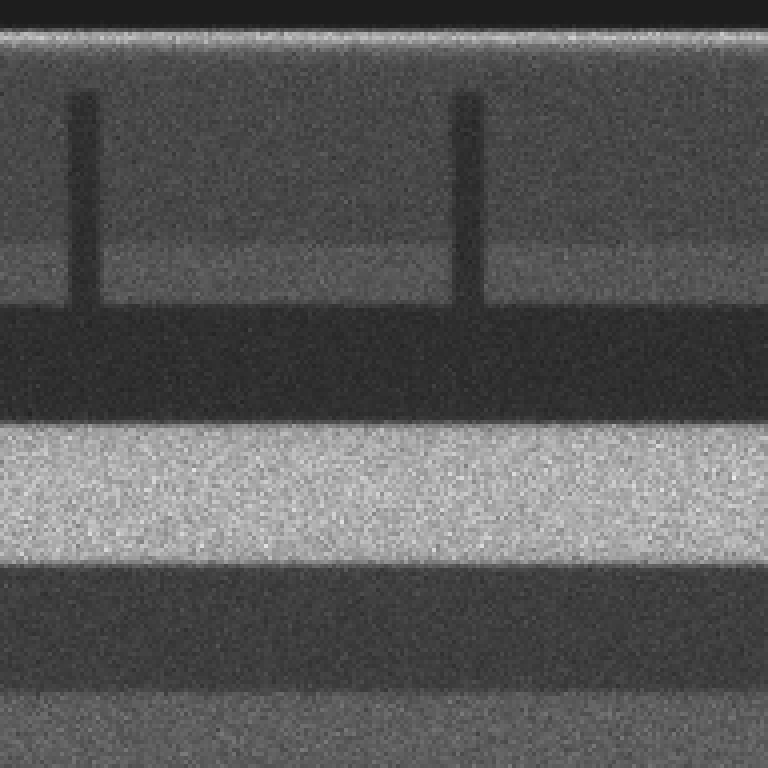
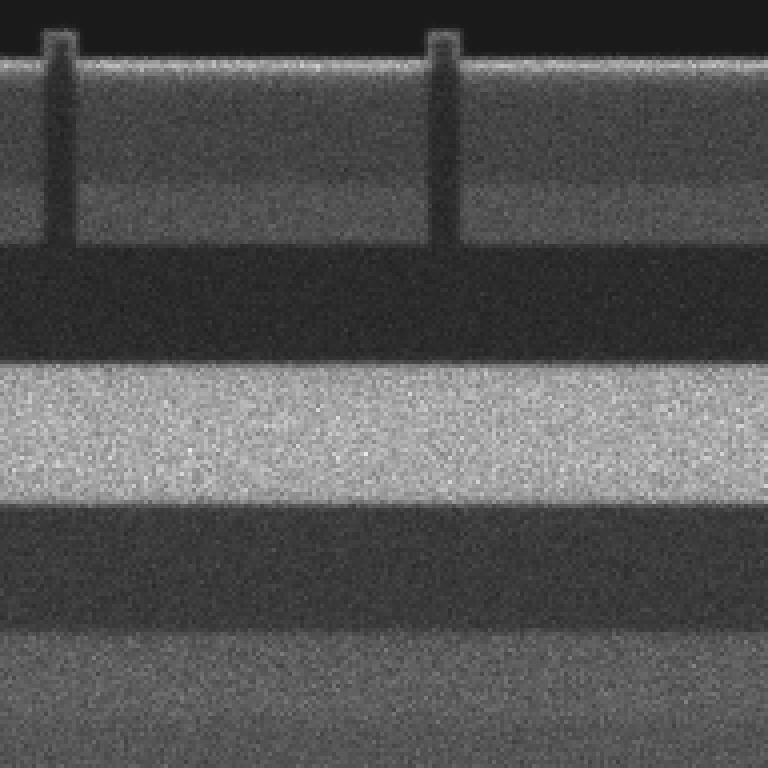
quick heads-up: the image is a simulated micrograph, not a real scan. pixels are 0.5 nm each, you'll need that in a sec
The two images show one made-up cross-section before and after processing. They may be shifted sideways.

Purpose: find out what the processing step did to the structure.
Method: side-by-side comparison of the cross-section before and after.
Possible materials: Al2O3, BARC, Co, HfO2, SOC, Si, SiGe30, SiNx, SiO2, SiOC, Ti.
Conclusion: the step removed SOC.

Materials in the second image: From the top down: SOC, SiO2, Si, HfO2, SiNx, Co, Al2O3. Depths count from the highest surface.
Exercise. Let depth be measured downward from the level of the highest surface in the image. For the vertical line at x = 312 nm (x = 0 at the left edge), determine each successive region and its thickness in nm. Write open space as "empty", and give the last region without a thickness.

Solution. empty 14, SOC 62, SiO2 30, Si 60, HfO2 70, SiNx 64, Co 44, Al2O3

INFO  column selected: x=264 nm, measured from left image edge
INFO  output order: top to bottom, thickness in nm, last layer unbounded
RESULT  empty 14, SOC 62, SiO2 30, Si 60, HfO2 70, SiNx 64, Co 44, Al2O3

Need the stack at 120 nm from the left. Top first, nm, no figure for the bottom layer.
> empty 14, SOC 62, SiO2 30, Si 60, HfO2 70, SiNx 64, Co 44, Al2O3